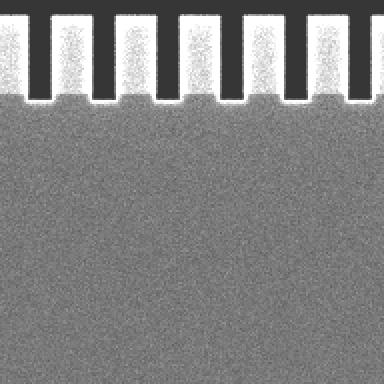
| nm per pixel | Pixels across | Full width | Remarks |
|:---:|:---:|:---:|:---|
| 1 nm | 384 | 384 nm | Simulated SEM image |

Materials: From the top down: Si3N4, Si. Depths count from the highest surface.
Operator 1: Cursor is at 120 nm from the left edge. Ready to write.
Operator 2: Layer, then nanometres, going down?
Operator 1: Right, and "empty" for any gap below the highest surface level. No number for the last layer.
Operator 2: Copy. Si3N4 78, Si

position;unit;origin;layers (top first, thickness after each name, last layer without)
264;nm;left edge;Si3N4 78, Si